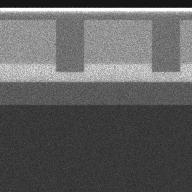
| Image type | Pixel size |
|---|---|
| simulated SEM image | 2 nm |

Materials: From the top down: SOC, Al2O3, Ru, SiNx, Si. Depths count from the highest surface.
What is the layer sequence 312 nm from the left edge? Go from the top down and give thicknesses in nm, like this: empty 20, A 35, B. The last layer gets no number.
SOC 128, Ru 20, SiNx 46, Si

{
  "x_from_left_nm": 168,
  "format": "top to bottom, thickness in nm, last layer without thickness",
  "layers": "SOC 24, Al2O3 88, Ru 36, SiNx 46, Si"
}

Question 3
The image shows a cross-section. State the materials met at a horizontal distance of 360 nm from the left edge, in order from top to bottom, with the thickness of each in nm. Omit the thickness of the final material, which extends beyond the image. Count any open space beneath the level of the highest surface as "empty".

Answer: SOC 24, Al2O3 88, Ru 36, SiNx 46, Si